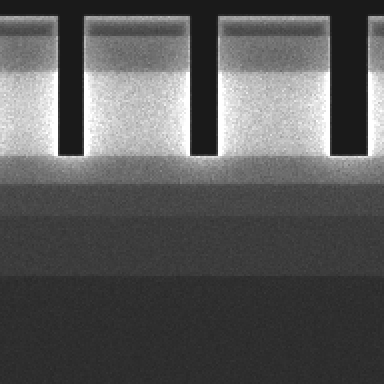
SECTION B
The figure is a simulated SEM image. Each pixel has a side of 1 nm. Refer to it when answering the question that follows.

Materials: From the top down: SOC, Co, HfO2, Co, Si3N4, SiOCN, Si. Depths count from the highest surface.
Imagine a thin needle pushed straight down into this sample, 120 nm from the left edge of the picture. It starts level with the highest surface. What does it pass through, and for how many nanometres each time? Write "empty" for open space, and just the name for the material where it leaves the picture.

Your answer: SOC 20, Co 36, HfO2 84, Co 28, Si3N4 32, SiOCN 60, Si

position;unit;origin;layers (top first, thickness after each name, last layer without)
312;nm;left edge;SOC 20, Co 36, HfO2 84, Co 28, Si3N4 32, SiOCN 60, Si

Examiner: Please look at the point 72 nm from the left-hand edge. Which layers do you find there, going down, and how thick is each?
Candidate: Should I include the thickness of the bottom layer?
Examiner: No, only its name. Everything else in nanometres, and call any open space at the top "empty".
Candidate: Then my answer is empty 140, Co 28, Si3N4 32, SiOCN 60, Si